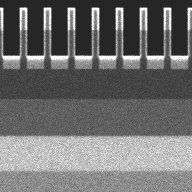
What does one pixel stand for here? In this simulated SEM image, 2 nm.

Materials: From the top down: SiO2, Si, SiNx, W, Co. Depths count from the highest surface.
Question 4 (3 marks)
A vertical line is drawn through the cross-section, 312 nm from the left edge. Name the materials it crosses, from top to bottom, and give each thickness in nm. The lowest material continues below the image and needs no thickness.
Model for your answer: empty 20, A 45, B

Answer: empty 96, SiO2 26, Si 60, SiNx 74, W 70, Co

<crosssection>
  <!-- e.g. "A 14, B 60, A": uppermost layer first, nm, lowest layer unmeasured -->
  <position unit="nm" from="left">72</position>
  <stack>empty 96, SiO2 26, Si 60, SiNx 74, W 70, Co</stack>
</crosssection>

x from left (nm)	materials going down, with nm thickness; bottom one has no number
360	empty 96, SiO2 26, Si 60, SiNx 74, W 70, Co